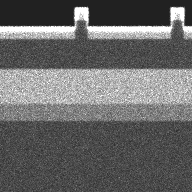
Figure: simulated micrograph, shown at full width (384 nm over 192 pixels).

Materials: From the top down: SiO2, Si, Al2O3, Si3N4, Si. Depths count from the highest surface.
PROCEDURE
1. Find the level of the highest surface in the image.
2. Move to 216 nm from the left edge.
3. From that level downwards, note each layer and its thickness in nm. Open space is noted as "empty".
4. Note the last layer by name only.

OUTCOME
empty 38, SiO2 24, Si 60, Al2O3 70, Si3N4 34, Si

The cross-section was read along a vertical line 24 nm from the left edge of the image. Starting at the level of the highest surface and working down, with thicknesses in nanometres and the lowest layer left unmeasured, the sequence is empty 38, SiO2 24, Si 60, Al2O3 70, Si3N4 34, Si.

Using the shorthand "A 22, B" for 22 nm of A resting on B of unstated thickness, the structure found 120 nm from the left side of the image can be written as empty 38, SiO2 24, Si 60, Al2O3 70, Si3N4 34, Si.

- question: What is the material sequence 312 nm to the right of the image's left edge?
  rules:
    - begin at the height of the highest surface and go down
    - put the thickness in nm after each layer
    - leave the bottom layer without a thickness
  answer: empty 38, SiO2 24, Si 60, Al2O3 70, Si3N4 34, Si